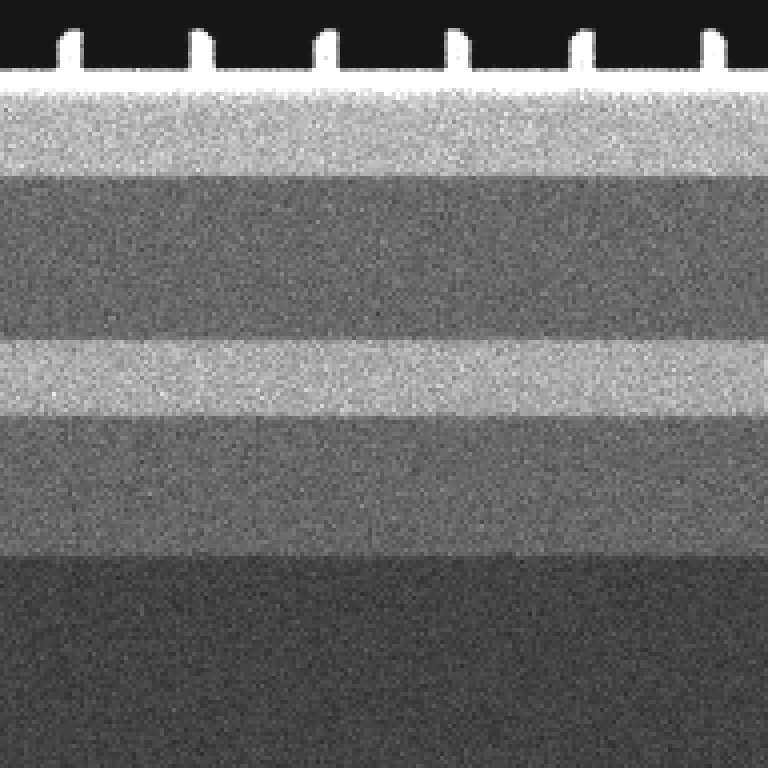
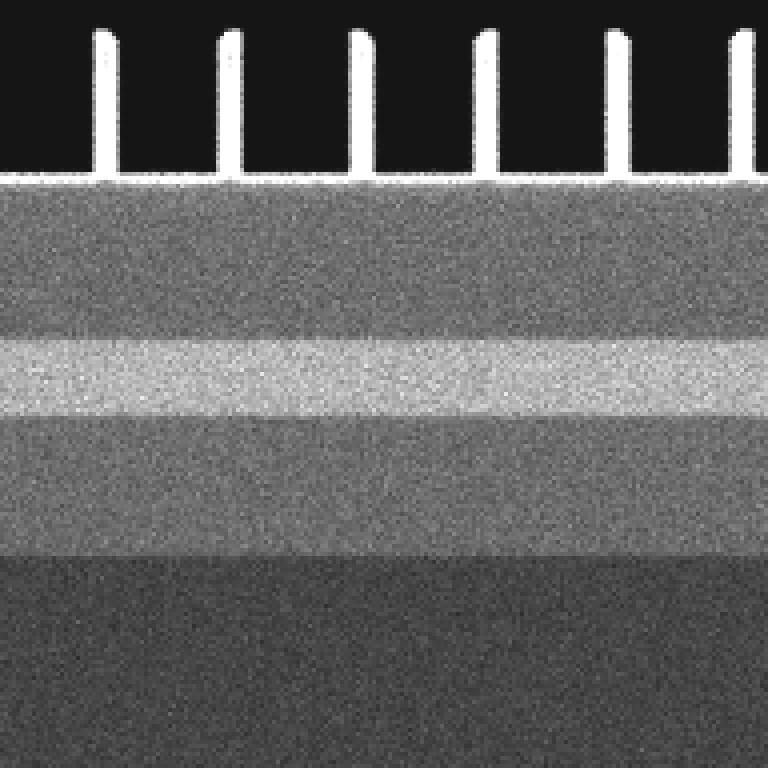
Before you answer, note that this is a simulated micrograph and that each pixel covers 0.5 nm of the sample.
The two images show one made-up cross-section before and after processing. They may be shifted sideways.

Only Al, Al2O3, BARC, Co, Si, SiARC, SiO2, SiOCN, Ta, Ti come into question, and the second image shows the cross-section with SiO2 removed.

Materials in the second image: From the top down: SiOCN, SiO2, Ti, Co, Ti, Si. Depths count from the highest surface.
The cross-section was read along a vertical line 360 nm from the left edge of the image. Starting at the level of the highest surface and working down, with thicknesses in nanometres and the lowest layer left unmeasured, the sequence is empty 72, Ti 82, Co 38, Ti 70, Si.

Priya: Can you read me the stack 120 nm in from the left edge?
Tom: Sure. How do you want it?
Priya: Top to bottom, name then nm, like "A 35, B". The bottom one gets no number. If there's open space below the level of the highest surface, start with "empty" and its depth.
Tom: empty 72, Ti 82, Co 38, Ti 70, Si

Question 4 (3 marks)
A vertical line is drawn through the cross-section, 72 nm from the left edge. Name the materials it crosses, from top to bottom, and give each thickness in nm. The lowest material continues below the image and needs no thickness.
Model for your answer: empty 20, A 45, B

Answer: empty 72, Ti 82, Co 38, Ti 70, Si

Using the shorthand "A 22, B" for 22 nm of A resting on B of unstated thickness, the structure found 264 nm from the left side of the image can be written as empty 72, Ti 82, Co 38, Ti 70, Si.